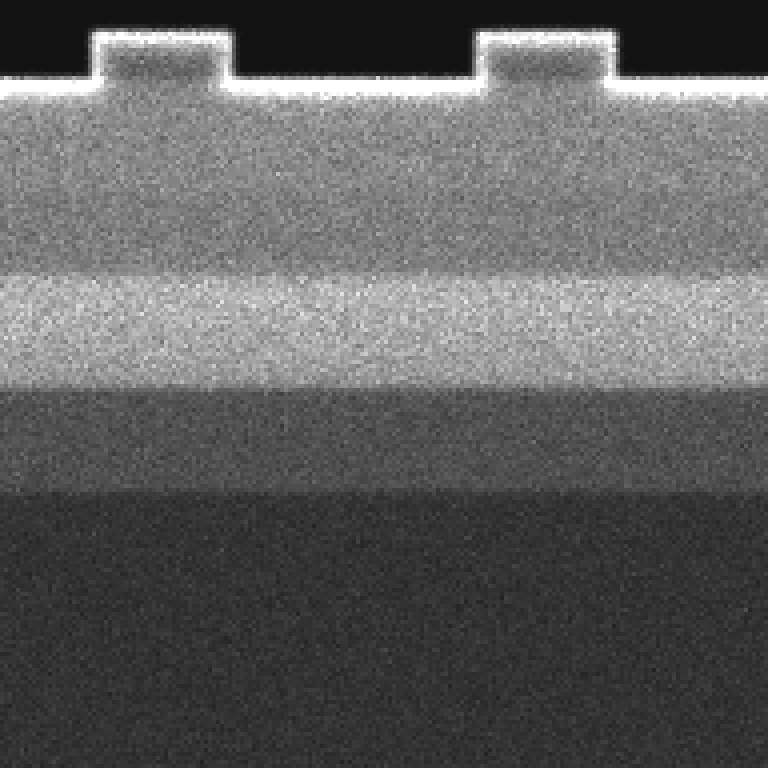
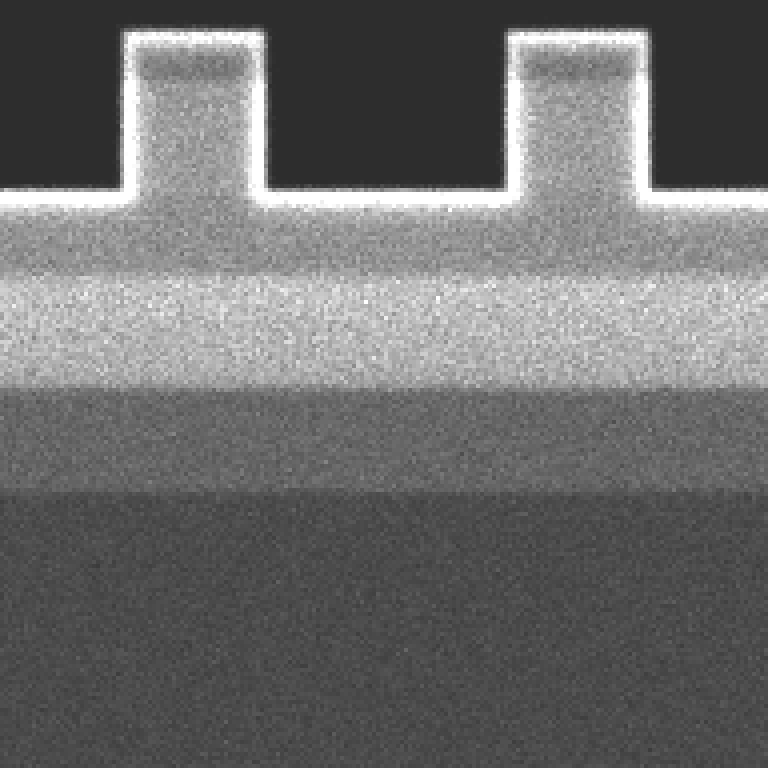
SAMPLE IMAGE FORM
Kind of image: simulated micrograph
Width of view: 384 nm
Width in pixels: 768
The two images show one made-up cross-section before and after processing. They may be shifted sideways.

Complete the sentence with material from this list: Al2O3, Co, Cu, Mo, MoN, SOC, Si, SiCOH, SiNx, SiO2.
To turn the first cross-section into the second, Al2O3 must be removed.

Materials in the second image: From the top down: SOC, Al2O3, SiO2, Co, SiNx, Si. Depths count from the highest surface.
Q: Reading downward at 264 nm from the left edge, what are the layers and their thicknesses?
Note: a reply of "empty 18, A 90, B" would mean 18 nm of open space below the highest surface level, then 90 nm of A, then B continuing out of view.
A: SOC 24, Al2O3 56, SiO2 42, Co 56, SiNx 52, Si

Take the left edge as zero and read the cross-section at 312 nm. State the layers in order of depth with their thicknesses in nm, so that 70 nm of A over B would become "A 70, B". SOC 24, Al2O3 56, SiO2 42, Co 56, SiNx 52, Si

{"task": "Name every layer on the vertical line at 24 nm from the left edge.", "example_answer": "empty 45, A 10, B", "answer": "empty 80, SiO2 42, Co 56, SiNx 52, Si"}